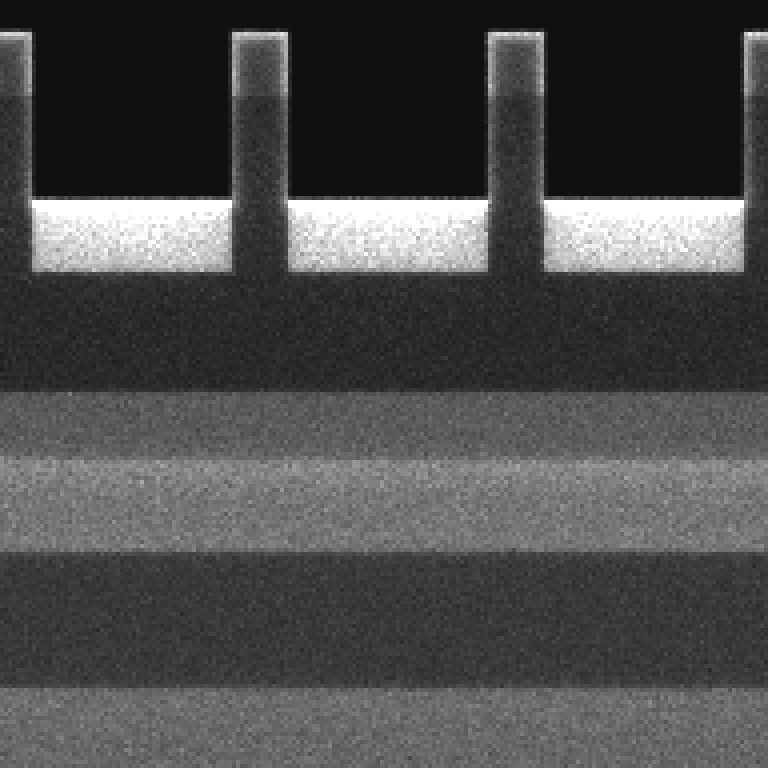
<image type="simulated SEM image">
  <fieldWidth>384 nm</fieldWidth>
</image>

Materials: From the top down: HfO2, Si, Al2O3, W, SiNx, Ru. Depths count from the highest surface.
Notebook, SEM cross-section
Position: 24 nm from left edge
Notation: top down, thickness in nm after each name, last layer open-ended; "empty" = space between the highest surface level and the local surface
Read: empty 84, HfO2 36, Si 60, Al2O3 34, W 46, SiNx 68, Ru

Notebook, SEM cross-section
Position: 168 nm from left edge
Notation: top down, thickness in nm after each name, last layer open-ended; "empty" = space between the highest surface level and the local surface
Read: empty 84, HfO2 36, Si 60, Al2O3 34, W 46, SiNx 68, Ru